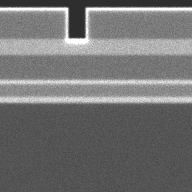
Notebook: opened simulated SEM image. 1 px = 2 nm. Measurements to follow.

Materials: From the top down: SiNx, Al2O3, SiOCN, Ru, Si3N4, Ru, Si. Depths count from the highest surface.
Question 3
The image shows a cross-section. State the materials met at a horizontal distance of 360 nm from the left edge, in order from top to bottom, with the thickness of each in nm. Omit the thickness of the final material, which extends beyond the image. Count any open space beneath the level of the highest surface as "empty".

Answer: SiNx 62, Al2O3 32, SiOCN 50, Ru 8, Si3N4 26, Ru 12, Si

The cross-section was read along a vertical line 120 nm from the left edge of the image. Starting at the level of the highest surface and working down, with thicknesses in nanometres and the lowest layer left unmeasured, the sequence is SiNx 62, Al2O3 32, SiOCN 50, Ru 8, Si3N4 26, Ru 12, Si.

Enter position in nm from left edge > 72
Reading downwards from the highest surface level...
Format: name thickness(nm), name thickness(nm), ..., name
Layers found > SiNx 62, Al2O3 32, SiOCN 50, Ru 8, Si3N4 26, Ru 12, Si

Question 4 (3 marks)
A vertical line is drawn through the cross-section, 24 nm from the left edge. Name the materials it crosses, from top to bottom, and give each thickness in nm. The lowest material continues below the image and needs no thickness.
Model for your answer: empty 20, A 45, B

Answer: SiNx 62, Al2O3 32, SiOCN 50, Ru 8, Si3N4 26, Ru 12, Si